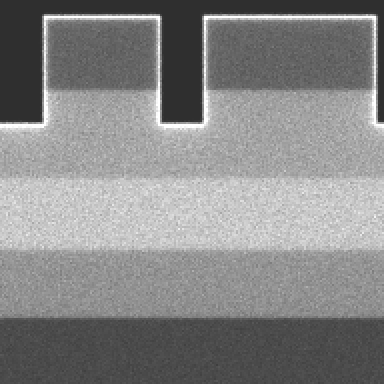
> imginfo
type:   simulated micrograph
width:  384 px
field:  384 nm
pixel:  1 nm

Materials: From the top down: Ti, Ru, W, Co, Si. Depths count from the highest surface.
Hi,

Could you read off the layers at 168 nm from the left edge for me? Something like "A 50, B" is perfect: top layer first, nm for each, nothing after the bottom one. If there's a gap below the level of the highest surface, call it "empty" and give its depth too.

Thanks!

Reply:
empty 108, Ru 54, W 72, Co 68, Si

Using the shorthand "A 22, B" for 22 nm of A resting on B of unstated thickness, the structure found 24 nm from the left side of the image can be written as empty 108, Ru 54, W 72, Co 68, Si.